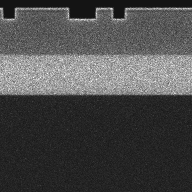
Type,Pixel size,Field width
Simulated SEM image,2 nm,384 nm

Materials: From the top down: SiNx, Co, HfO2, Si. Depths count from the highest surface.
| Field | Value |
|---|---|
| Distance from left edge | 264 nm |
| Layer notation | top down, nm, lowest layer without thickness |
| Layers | SiNx 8, Co 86, HfO2 80, Si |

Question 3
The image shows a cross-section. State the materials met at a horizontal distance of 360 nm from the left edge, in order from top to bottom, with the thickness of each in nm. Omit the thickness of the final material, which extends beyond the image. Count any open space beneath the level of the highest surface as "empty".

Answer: SiNx 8, Co 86, HfO2 80, Si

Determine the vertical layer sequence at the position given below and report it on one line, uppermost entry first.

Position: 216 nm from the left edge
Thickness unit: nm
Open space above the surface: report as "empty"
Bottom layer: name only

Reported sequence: SiNx 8, Co 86, HfO2 80, Si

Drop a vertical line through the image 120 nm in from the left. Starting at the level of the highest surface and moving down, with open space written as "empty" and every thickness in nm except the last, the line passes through SiNx 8, Co 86, HfO2 80, Si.